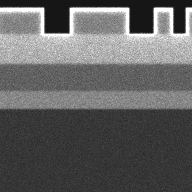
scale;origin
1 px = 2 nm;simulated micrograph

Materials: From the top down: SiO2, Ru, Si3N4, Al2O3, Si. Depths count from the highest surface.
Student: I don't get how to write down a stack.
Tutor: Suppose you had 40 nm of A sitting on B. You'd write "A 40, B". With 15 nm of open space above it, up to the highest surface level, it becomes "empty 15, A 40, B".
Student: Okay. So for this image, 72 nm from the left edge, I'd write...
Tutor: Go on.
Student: SiO2 52, Ru 60, Si3N4 54, Al2O3 36, Si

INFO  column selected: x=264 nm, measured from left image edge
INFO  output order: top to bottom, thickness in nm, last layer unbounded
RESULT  empty 52, Ru 60, Si3N4 54, Al2O3 36, Si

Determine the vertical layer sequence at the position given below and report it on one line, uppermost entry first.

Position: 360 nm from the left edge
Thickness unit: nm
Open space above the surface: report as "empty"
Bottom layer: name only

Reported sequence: empty 52, Ru 60, Si3N4 54, Al2O3 36, Si